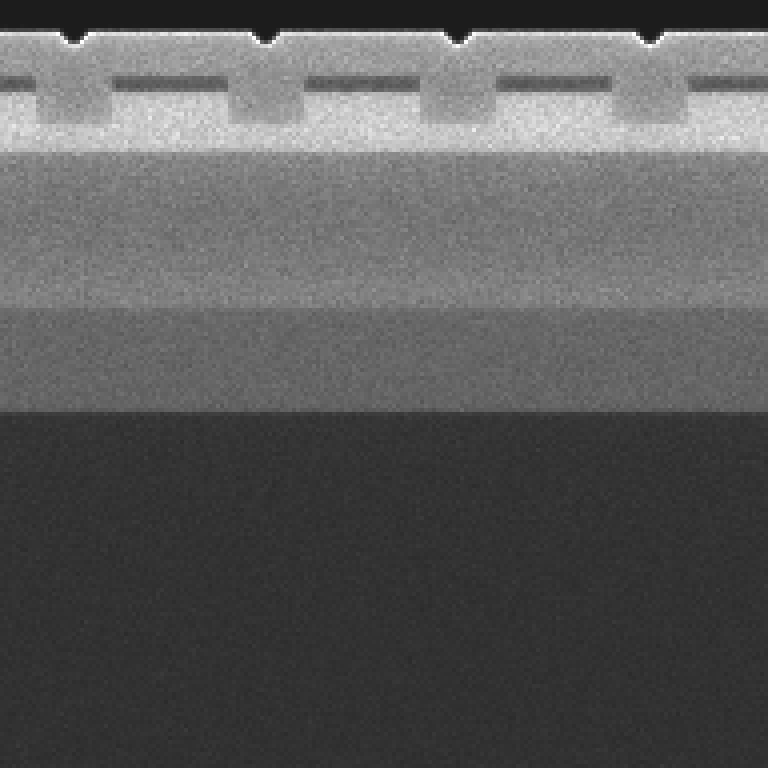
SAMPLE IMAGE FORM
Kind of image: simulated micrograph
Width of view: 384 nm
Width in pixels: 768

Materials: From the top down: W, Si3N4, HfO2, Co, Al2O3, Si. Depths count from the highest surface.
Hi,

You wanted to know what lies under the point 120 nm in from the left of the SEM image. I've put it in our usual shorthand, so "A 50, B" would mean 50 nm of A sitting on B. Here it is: W 46, HfO2 14, Co 78, Al2O3 52, Si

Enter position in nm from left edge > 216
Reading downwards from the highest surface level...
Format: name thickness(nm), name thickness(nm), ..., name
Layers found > W 46, HfO2 14, Co 78, Al2O3 52, Si